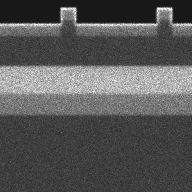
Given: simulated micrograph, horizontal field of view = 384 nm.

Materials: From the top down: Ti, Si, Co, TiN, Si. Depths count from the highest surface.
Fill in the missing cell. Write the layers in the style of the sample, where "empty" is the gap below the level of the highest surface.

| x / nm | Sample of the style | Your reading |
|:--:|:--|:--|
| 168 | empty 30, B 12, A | empty 32, Ti 24, Si 60, Co 56, TiN 42, Si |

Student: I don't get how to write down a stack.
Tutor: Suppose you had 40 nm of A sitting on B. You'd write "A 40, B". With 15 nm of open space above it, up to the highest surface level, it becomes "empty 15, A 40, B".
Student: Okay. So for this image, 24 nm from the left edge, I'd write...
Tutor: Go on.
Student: empty 32, Ti 24, Si 60, Co 56, TiN 42, Si